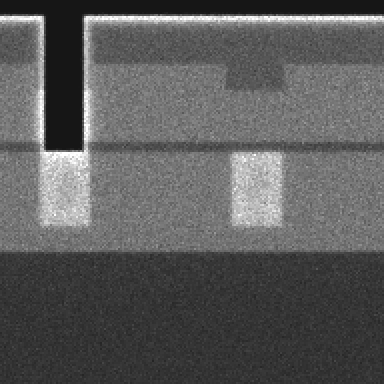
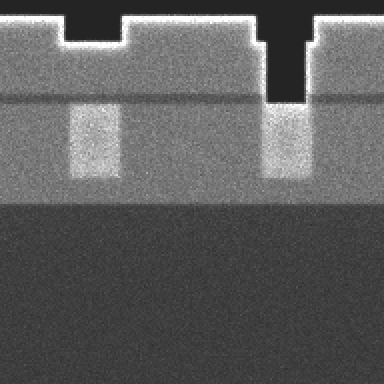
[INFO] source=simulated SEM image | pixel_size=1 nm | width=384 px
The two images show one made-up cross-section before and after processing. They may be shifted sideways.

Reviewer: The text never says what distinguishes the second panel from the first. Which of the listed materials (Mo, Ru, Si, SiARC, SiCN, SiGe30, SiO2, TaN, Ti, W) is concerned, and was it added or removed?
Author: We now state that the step removed SiARC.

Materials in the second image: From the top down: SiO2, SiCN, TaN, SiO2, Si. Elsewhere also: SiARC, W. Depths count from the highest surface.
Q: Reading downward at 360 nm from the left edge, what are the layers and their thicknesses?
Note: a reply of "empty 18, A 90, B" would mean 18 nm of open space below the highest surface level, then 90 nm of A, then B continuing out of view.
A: SiO2 78, SiCN 10, SiO2 100, Si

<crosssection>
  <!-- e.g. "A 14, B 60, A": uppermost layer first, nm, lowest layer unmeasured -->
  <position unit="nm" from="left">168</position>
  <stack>SiO2 78, SiCN 10, SiO2 100, Si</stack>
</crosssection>